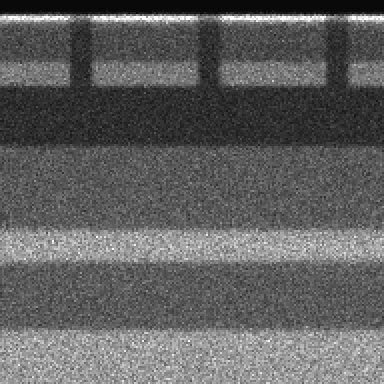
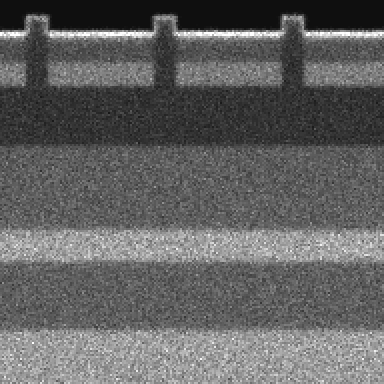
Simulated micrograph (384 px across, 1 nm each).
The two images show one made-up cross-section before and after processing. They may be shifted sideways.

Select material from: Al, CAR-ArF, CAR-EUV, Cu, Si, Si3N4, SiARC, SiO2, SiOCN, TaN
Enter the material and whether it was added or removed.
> SiOCN / removed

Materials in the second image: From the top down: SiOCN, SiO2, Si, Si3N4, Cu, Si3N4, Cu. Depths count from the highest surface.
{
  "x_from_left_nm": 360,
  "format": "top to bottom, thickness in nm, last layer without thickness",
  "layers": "empty 16, SiOCN 30, SiO2 24, Si 60, Si3N4 84, Cu 32, Si3N4 68, Cu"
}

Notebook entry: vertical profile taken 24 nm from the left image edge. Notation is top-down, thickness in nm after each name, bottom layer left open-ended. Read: empty 16, SiOCN 30, SiO2 24, Si 60, Si3N4 84, Cu 32, Si3N4 68, Cu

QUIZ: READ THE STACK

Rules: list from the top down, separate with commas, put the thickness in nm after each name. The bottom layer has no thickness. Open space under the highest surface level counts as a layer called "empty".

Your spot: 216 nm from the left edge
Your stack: empty 16, SiOCN 30, SiO2 24, Si 60, Si3N4 84, Cu 32, Si3N4 68, Cu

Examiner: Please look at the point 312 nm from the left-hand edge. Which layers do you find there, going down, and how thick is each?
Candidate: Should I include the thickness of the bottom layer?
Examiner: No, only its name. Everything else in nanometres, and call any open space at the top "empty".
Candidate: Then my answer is empty 16, SiOCN 30, SiO2 24, Si 60, Si3N4 84, Cu 32, Si3N4 68, Cu